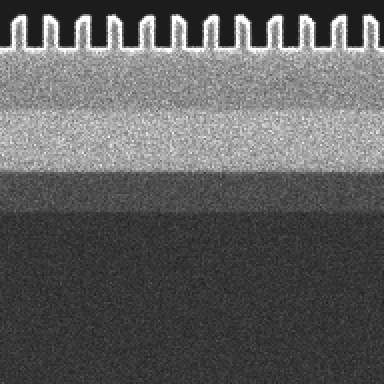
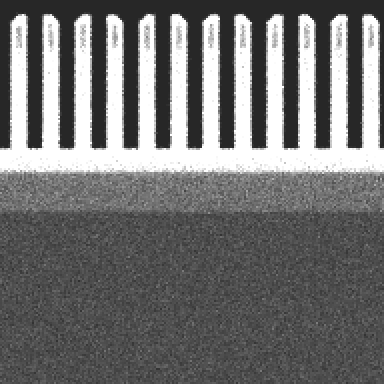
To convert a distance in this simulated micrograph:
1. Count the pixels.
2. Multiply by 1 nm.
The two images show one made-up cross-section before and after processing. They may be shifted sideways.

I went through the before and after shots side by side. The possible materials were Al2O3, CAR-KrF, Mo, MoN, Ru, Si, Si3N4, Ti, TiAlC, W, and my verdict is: removed, Ru and W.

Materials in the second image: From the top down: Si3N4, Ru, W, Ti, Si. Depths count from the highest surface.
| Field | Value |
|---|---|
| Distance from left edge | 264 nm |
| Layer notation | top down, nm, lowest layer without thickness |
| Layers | empty 134, W 22, Ti 40, Si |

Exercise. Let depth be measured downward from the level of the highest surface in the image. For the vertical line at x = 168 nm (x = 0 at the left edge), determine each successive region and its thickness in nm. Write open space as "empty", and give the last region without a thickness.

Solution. empty 134, W 22, Ti 40, Si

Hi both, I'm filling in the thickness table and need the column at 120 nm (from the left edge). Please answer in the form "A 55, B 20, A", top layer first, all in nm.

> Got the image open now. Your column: empty 6, Si3N4 26, Ru 62, W 62, Ti 40, Si